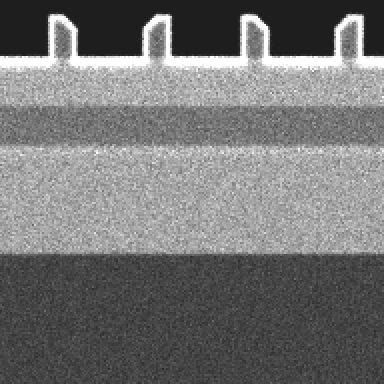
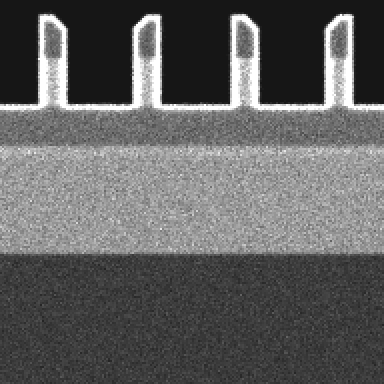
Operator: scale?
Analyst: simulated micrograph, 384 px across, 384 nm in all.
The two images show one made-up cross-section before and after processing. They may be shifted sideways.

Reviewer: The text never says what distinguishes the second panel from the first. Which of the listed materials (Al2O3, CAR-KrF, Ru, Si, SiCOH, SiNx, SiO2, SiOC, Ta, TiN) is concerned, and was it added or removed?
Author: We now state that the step removed Al2O3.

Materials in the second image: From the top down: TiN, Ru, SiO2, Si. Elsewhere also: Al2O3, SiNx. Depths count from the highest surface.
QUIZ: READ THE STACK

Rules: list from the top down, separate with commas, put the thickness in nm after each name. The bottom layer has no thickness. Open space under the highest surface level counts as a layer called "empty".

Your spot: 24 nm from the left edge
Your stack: empty 90, TiN 40, Ru 10, SiO2 98, Si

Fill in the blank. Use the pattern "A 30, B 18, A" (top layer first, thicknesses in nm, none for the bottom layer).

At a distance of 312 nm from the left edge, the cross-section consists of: empty 90, TiN 40, Ru 10, SiO2 98, Si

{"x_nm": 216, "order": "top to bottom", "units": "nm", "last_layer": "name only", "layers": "empty 90, TiN 40, Ru 10, SiO2 98, Si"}